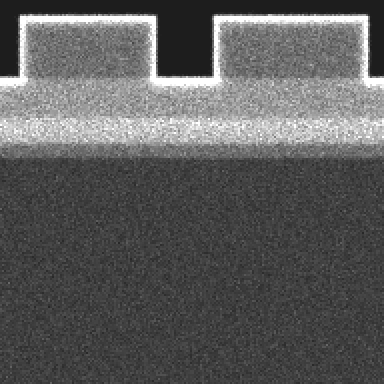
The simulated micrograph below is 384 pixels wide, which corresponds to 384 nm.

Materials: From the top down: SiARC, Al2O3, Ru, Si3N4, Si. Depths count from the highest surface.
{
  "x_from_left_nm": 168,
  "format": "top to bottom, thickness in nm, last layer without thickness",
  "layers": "empty 62, Al2O3 40, Ru 26, Si3N4 14, Si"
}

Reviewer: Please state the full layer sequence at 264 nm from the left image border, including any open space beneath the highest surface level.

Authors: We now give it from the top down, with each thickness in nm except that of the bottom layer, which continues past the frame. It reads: SiARC 62, Al2O3 40, Ru 26, Si3N4 14, Si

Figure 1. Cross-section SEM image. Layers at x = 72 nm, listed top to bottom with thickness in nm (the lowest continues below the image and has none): SiARC 62, Al2O3 40, Ru 26, Si3N4 14, Si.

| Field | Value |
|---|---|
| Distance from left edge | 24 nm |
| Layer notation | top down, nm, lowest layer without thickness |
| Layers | SiARC 62, Al2O3 40, Ru 26, Si3N4 14, Si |